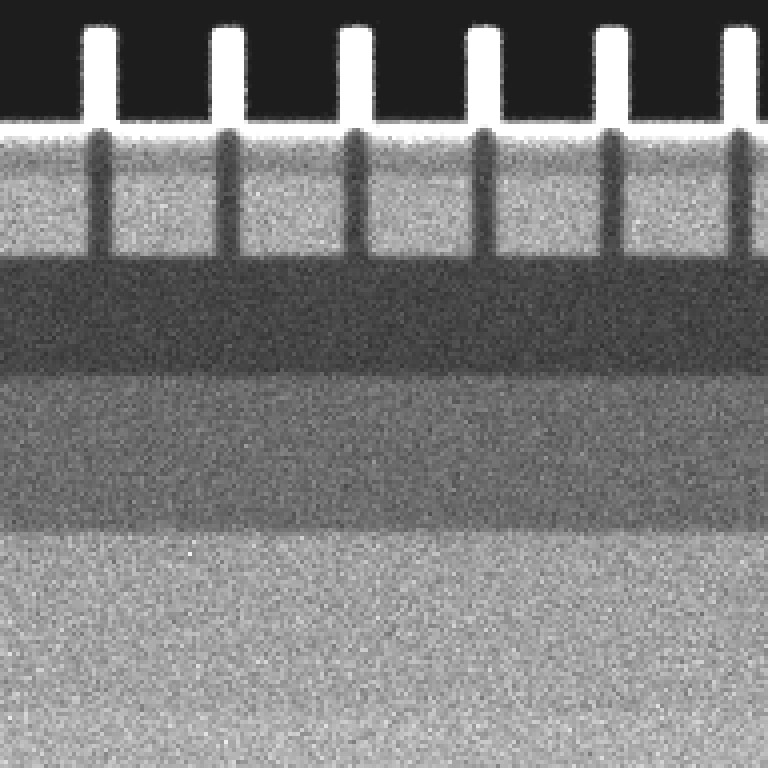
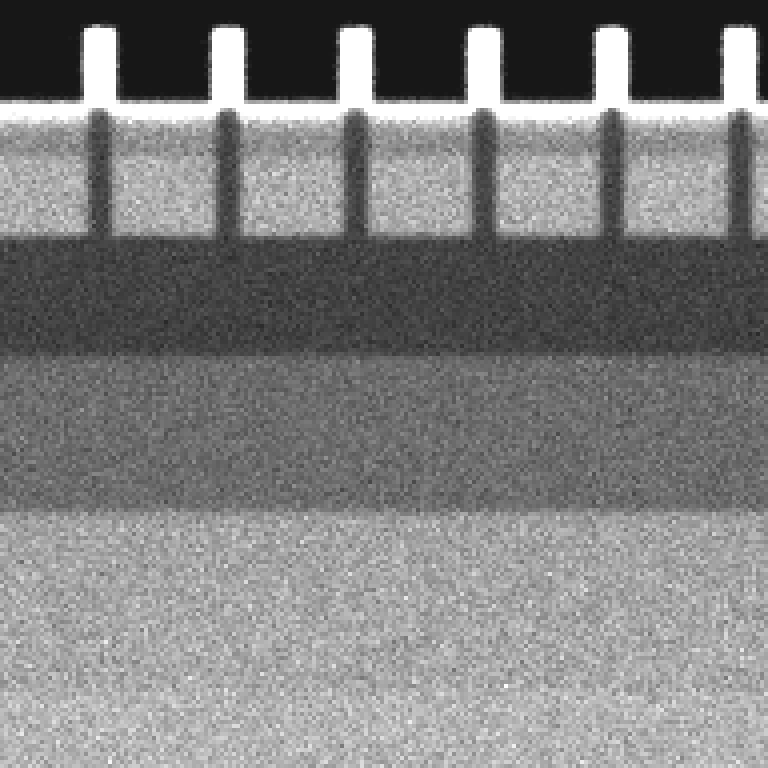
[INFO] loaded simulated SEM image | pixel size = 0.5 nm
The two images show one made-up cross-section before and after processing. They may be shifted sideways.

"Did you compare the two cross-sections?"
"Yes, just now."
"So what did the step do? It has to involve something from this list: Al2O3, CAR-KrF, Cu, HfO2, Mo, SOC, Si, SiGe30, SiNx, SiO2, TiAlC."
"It removed HfO2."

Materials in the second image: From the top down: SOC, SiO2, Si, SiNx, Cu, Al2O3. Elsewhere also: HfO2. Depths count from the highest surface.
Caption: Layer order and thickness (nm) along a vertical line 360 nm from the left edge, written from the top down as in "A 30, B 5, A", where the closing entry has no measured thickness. empty 36, SOC 26, SiO2 40, Si 60, SiNx 78, Cu 90, Al2O3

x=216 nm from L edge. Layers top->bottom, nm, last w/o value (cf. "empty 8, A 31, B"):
empty 36, SOC 26, SiO2 40, Si 60, SiNx 78, Cu 90, Al2O3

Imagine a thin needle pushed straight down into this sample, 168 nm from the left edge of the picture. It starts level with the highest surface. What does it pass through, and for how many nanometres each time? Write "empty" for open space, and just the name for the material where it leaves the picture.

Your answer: empty 36, SOC 26, SiO2 40, Si 60, SiNx 78, Cu 90, Al2O3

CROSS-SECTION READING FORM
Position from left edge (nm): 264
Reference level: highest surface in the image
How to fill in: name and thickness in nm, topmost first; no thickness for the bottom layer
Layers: empty 36, SOC 26, SiO2 40, Si 60, SiNx 78, Cu 90, Al2O3